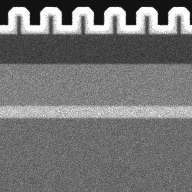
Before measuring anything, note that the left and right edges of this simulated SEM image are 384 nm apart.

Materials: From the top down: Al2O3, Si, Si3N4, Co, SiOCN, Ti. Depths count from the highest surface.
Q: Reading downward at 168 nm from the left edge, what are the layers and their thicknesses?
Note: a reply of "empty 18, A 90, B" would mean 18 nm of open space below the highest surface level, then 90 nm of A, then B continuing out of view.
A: Al2O3 16, Si 96, Si3N4 84, Co 24, SiOCN 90, Ti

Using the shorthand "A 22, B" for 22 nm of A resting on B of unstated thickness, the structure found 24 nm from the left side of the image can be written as empty 2, Al2O3 50, Si 60, Si3N4 84, Co 24, SiOCN 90, Ti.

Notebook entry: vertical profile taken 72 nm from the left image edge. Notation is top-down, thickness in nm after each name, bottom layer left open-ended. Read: empty 36, Al2O3 16, Si 60, Si3N4 84, Co 24, SiOCN 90, Ti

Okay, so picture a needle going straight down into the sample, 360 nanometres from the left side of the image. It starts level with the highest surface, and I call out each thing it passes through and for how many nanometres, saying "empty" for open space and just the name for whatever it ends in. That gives Al2O3 16, Si 96, Si3N4 84, Co 24, SiOCN 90, Ti